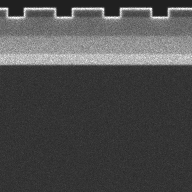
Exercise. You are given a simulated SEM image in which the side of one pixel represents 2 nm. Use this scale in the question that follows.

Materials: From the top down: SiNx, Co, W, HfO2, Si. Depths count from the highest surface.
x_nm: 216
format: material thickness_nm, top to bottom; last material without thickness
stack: empty 18, Co 38, W 36, HfO2 22, Si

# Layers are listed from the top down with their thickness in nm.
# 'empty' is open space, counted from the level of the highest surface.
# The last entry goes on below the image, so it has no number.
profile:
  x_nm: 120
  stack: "empty 18, Co 38, W 36, HfO2 22, Si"